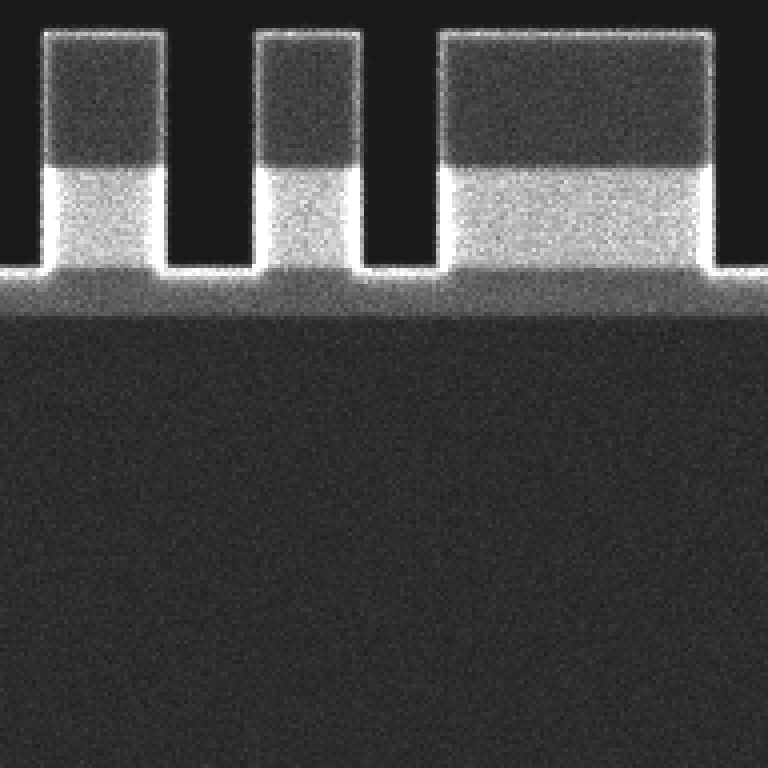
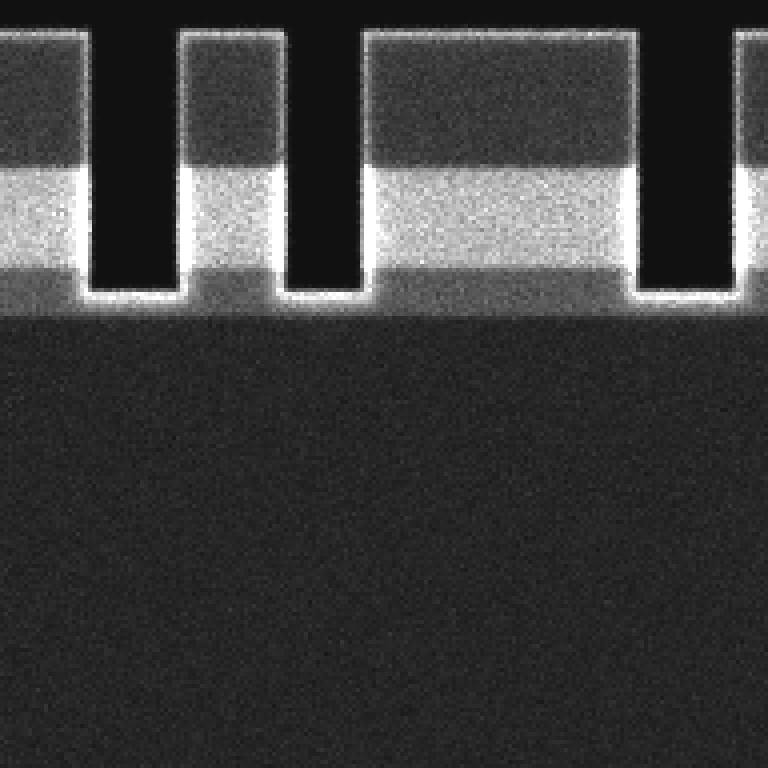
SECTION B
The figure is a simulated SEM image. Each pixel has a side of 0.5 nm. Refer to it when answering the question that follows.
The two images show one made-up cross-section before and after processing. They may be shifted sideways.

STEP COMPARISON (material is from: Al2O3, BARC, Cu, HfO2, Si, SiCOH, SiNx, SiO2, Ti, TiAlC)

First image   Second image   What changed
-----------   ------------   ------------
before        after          SiO2, removed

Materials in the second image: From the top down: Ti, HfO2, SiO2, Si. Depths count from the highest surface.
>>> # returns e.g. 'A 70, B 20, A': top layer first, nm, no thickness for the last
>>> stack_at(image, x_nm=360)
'empty 130, SiO2 12, Si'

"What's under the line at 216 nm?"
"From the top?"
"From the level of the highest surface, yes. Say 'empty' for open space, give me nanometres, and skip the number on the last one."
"Ti 68, HfO2 50, SiO2 24, Si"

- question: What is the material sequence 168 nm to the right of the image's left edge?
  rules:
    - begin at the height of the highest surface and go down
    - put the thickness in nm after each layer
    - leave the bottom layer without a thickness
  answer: empty 130, SiO2 12, Si